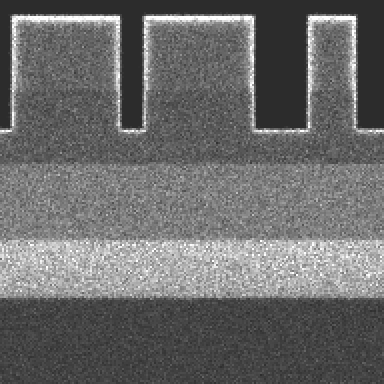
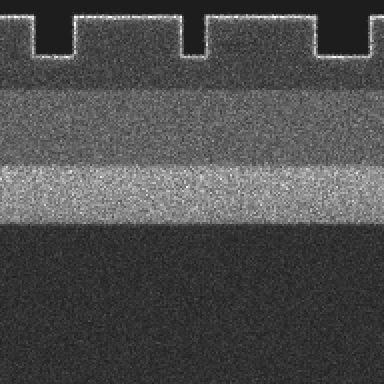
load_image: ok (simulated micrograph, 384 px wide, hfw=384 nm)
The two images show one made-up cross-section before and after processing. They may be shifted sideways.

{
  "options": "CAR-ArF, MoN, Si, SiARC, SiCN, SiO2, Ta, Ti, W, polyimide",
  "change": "removed",
  "material": "SiARC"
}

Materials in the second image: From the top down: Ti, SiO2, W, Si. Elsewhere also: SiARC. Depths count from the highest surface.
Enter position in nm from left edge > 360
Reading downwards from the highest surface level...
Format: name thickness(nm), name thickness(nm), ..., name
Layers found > empty 40, Ti 34, SiO2 76, W 58, Si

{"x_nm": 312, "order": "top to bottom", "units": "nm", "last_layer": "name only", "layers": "Ti 74, SiO2 76, W 58, Si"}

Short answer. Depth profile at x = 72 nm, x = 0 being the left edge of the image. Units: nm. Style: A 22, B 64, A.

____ empty 40, Ti 34, SiO2 76, W 58, Si